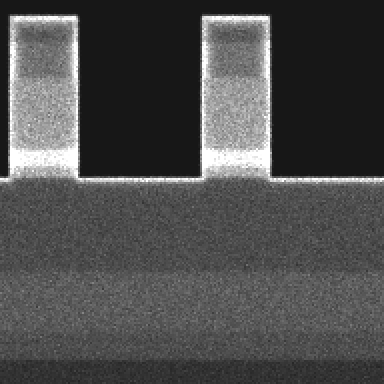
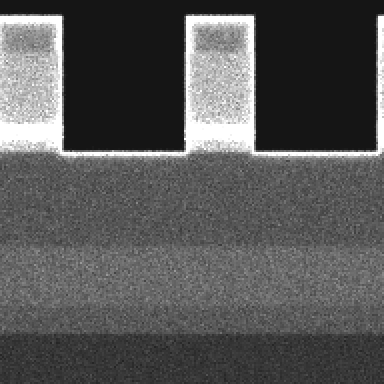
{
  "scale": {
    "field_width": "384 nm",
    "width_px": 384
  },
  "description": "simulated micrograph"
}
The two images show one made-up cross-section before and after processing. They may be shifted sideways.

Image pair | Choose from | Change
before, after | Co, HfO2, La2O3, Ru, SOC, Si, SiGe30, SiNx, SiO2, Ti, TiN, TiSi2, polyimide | SOC (removed)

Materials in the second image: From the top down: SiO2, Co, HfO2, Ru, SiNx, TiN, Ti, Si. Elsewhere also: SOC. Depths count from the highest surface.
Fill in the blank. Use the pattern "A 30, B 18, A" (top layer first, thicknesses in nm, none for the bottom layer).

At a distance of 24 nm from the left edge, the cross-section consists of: SiO2 36, Co 72, HfO2 16, Ru 12, SiNx 94, TiN 60, Ti 28, Si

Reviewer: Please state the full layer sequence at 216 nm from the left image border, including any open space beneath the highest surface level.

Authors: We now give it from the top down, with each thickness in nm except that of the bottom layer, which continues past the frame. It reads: SiO2 36, Co 72, HfO2 16, Ru 12, SiNx 94, TiN 60, Ti 28, Si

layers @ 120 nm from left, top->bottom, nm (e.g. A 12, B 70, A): empty 136, SiNx 94, TiN 60, Ti 28, Si